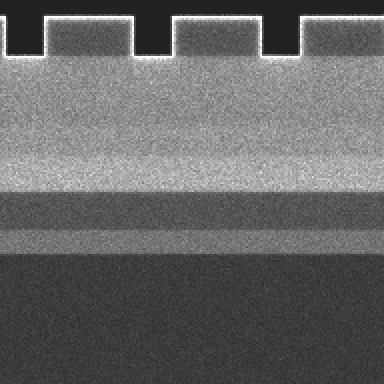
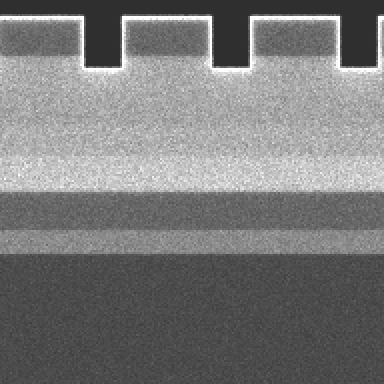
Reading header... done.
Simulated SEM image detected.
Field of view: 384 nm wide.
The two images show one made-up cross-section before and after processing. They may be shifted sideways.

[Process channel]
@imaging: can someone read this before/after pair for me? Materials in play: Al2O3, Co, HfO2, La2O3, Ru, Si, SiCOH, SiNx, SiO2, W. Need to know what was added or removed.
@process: Co removed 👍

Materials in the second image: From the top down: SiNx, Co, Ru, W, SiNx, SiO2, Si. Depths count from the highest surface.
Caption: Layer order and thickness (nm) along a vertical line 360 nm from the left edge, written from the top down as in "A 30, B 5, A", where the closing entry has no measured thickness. empty 52, Co 58, Ru 30, W 36, SiNx 38, SiO2 24, Si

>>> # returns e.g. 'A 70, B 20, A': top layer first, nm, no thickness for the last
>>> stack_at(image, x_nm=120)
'empty 52, Co 58, Ru 30, W 36, SiNx 38, SiO2 24, Si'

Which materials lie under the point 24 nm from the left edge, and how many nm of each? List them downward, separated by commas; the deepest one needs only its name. SiNx 40, Co 70, Ru 30, W 36, SiNx 38, SiO2 24, Si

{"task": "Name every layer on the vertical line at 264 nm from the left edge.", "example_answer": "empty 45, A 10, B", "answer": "SiNx 40, Co 70, Ru 30, W 36, SiNx 38, SiO2 24, Si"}